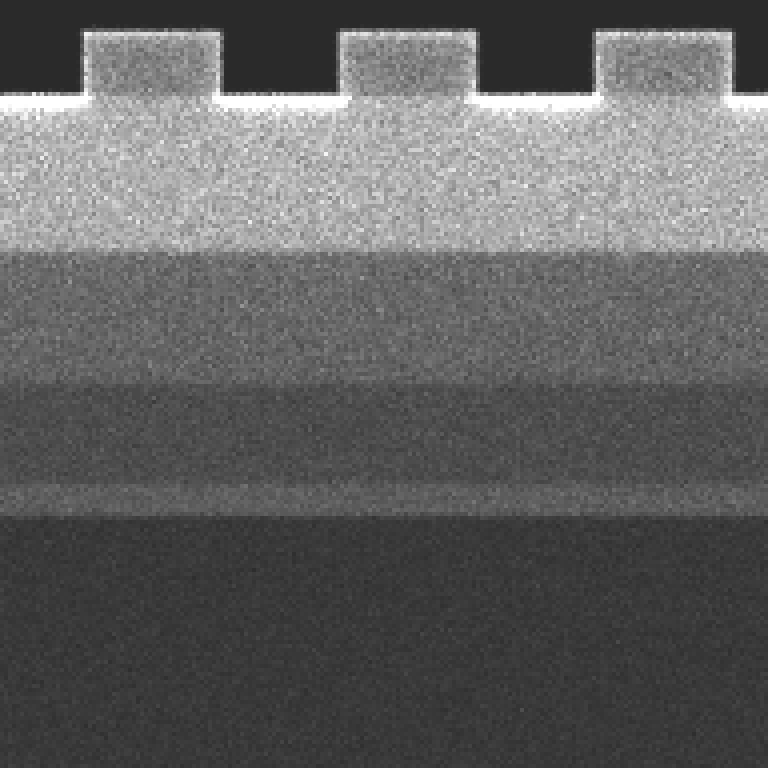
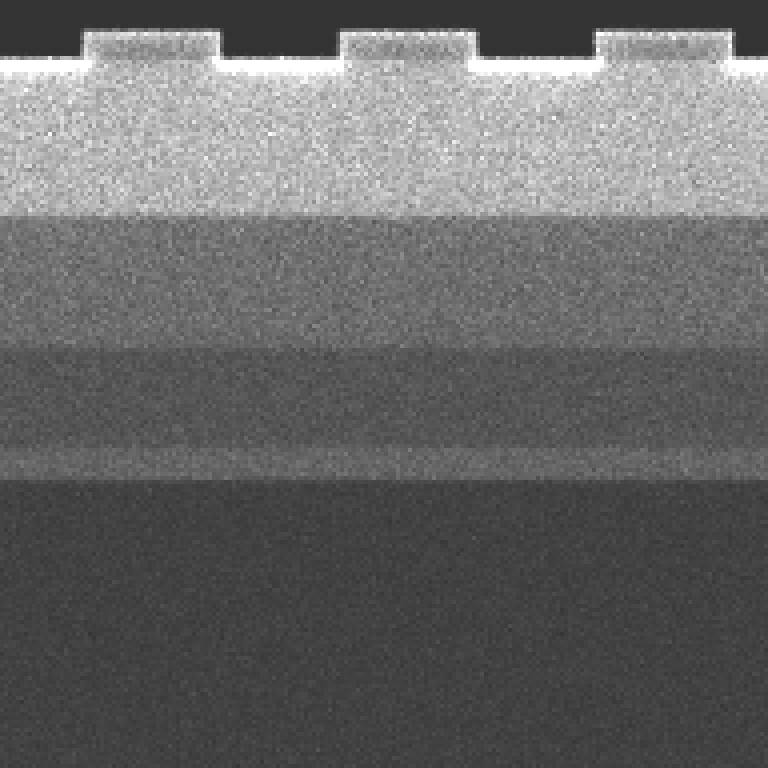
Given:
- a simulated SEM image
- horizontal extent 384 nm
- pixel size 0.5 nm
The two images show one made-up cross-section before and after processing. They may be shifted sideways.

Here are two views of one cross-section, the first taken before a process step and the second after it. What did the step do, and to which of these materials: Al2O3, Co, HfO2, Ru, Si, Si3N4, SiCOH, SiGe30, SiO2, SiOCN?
It removed Ru.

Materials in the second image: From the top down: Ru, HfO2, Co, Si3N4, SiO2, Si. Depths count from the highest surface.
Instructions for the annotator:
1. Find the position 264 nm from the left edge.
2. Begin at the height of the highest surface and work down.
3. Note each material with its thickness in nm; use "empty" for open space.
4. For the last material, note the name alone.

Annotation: empty 14, HfO2 78, Co 66, Si3N4 50, SiO2 16, Si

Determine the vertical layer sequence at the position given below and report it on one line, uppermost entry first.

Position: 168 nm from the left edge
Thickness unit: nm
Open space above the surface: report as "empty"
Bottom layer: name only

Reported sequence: empty 14, HfO2 78, Co 66, Si3N4 50, SiO2 16, Si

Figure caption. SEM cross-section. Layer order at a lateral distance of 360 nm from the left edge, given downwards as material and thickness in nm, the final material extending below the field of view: Ru 14, HfO2 78, Co 66, Si3N4 50, SiO2 16, Si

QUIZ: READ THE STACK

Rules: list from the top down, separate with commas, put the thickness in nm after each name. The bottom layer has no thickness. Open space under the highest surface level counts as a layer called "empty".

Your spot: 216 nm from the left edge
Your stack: Ru 14, HfO2 78, Co 66, Si3N4 50, SiO2 16, Si